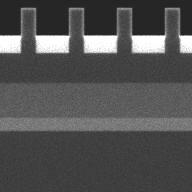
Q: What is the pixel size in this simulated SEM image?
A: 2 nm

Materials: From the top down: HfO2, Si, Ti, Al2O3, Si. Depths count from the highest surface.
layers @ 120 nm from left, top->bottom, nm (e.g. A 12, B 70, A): empty 56, HfO2 34, Si 60, Ti 70, Al2O3 26, Si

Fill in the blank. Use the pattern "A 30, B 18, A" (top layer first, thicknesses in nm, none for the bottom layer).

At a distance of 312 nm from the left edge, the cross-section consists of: empty 56, HfO2 34, Si 60, Ti 70, Al2O3 26, Si